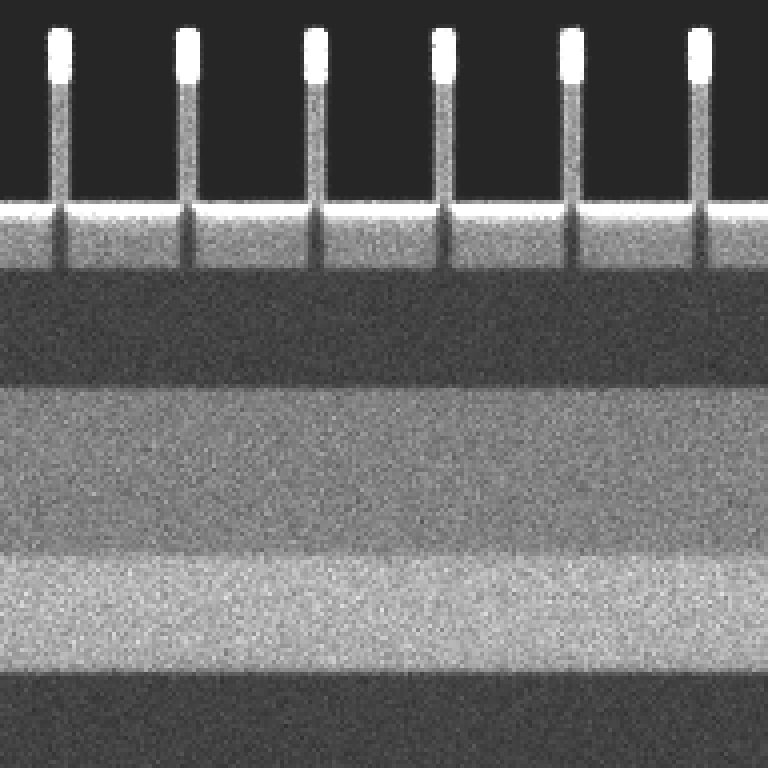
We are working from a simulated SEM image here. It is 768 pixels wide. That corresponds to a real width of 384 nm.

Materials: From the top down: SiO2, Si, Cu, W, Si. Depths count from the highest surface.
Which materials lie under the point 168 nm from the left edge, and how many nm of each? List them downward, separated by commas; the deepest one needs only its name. empty 86, SiO2 32, Si 60, Cu 84, W 58, Si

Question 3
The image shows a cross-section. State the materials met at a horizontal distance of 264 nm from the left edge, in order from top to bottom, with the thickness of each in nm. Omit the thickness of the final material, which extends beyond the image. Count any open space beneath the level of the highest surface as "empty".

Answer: empty 86, SiO2 32, Si 60, Cu 84, W 58, Si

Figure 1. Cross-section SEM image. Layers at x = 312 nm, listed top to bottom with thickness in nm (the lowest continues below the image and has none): empty 86, SiO2 32, Si 60, Cu 84, W 58, Si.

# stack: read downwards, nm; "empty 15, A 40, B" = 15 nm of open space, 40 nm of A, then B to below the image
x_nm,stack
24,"empty 86, SiO2 32, Si 60, Cu 84, W 58, Si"